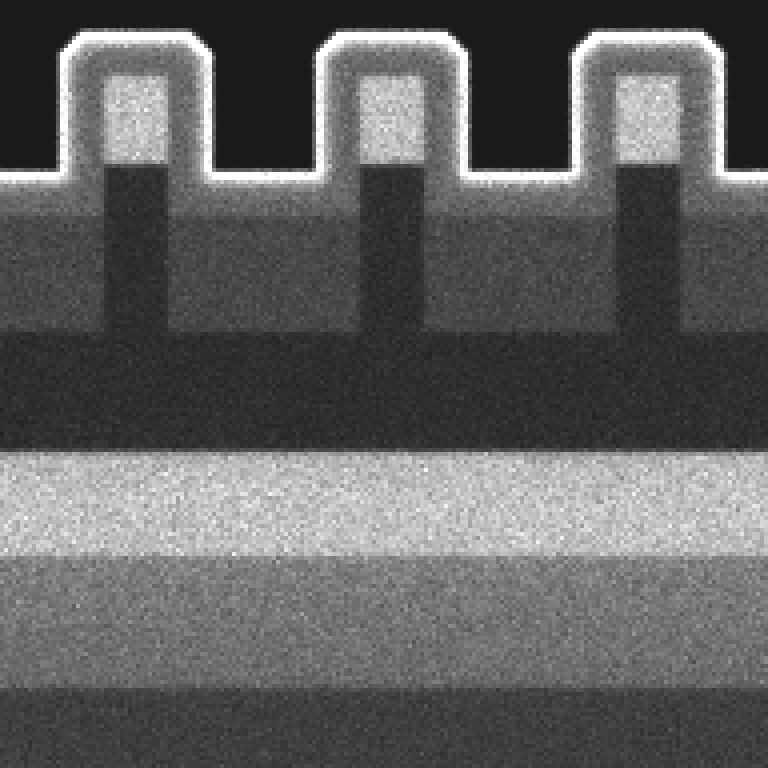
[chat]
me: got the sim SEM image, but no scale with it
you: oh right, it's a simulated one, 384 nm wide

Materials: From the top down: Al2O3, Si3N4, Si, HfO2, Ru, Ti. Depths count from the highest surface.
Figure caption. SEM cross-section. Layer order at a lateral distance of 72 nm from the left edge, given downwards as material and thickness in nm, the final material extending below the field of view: Al2O3 22, HfO2 44, Si 144, HfO2 52, Ru 66, Ti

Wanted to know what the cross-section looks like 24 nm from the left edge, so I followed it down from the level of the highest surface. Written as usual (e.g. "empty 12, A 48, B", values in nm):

empty 70, Al2O3 22, Si3N4 58, Si 60, HfO2 52, Ru 66, Ti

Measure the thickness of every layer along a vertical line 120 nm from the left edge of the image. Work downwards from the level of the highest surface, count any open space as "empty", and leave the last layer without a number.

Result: empty 70, Al2O3 22, Si3N4 58, Si 60, HfO2 52, Ru 66, Ti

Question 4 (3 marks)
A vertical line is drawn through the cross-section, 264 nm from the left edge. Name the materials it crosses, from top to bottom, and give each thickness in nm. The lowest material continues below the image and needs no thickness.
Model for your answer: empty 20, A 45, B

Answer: empty 70, Al2O3 22, Si3N4 58, Si 60, HfO2 52, Ru 66, Ti